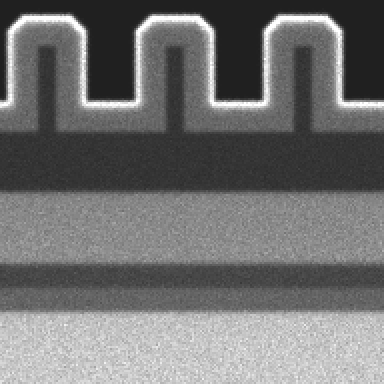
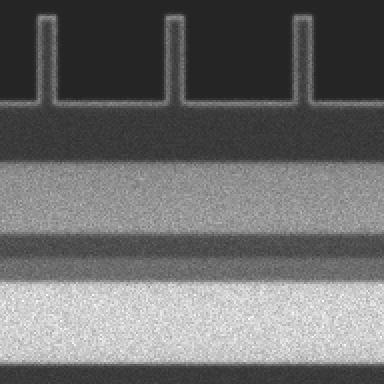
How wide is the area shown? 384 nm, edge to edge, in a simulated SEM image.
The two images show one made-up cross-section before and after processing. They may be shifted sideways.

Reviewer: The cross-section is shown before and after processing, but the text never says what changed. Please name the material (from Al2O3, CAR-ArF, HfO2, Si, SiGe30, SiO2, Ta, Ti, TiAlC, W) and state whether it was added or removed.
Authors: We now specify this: Al2O3, removed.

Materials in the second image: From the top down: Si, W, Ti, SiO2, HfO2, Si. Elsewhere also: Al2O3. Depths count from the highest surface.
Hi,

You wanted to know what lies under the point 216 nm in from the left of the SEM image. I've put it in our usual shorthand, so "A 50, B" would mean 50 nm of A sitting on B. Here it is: empty 86, Si 60, W 72, Ti 24, SiO2 24, HfO2 82, Si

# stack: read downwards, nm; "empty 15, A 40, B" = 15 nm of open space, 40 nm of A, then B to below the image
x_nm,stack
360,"empty 86, Si 60, W 72, Ti 24, SiO2 24, HfO2 82, Si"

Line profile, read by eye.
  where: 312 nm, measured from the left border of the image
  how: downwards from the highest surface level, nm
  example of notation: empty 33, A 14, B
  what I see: empty 86, Si 60, W 72, Ti 24, SiO2 24, HfO2 82, Si